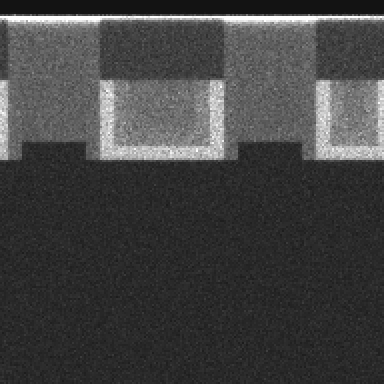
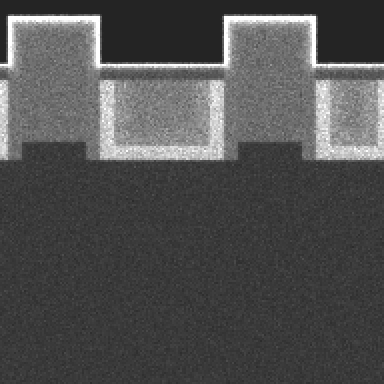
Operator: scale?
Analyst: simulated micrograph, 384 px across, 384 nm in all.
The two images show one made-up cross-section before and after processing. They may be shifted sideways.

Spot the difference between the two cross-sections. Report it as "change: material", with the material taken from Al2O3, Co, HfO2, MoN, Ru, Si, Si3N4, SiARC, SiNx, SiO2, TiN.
removed: SiNx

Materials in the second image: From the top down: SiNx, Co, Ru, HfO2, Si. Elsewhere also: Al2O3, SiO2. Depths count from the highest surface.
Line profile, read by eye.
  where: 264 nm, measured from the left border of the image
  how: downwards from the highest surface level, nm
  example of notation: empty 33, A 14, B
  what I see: SiO2 126, Si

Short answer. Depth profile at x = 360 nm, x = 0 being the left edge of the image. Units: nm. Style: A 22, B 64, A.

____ empty 48, SiNx 16, Co 52, Ru 14, HfO2 14, Si